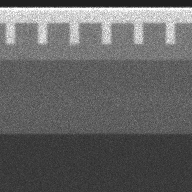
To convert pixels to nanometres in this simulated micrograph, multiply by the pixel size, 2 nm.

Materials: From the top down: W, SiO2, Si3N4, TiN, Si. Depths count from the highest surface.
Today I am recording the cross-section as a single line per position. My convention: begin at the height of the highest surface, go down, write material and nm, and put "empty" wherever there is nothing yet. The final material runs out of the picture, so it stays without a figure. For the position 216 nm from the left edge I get W 72, SiO2 32, Si3N4 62, TiN 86, Si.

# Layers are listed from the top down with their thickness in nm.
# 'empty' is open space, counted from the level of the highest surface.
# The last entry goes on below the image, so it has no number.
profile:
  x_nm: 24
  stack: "W 72, SiO2 32, Si3N4 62, TiN 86, Si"